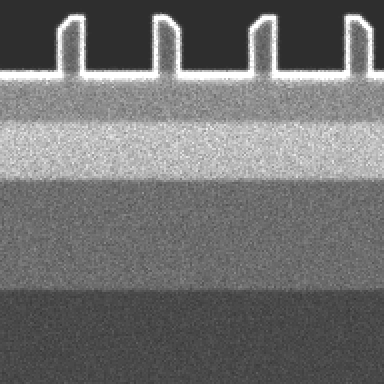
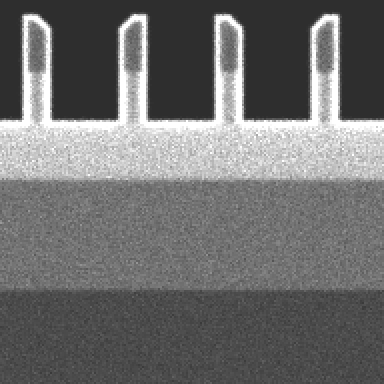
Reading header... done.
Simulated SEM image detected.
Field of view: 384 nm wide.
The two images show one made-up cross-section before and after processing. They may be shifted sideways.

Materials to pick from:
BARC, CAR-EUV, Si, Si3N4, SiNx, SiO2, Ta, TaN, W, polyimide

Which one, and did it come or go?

SiO2 - removed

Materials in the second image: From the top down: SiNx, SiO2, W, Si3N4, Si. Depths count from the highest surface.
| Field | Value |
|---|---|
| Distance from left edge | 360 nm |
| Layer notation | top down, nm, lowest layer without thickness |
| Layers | empty 106, W 58, Si3N4 110, Si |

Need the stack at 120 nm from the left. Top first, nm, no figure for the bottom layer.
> empty 12, SiNx 44, SiO2 50, W 58, Si3N4 110, Si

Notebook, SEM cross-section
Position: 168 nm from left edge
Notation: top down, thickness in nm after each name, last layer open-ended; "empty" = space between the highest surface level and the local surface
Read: empty 106, W 58, Si3N4 110, Si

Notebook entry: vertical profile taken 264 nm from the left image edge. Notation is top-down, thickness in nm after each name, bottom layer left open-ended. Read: empty 106, W 58, Si3N4 110, Si